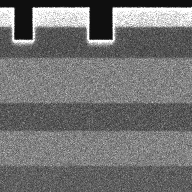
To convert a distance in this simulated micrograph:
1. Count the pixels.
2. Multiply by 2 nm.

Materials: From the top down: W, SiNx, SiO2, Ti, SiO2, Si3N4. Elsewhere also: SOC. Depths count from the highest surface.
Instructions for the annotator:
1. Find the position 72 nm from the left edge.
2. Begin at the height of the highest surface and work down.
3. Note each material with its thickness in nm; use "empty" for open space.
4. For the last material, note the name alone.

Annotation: W 38, SiNx 62, SiO2 90, Ti 56, SiO2 70, Si3N4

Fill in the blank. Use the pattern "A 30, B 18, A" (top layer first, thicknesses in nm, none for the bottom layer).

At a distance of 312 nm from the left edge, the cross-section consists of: W 38, SiNx 62, SiO2 90, Ti 56, SiO2 70, Si3N4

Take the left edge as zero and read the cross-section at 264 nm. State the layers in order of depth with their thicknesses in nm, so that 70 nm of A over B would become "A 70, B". W 38, SiNx 62, SiO2 90, Ti 56, SiO2 70, Si3N4